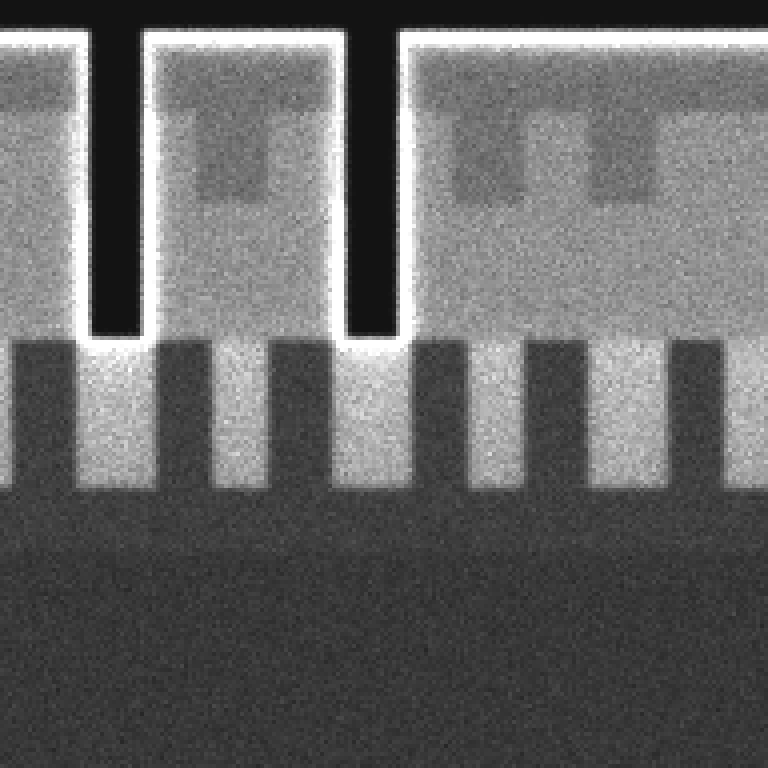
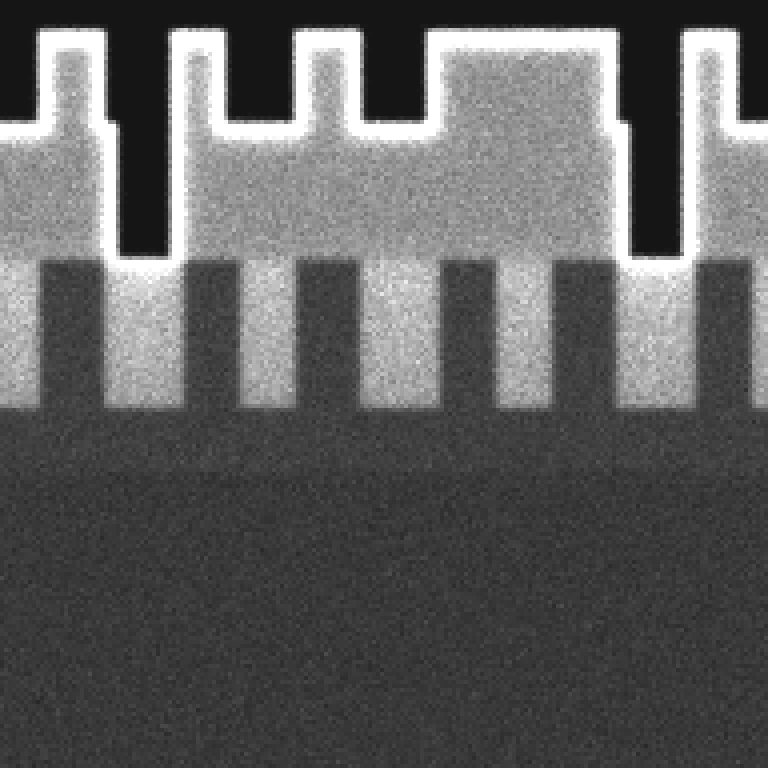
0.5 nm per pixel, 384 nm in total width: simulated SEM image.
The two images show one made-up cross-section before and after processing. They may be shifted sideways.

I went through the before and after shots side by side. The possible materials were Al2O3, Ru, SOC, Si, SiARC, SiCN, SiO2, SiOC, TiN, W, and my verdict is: removed, SOC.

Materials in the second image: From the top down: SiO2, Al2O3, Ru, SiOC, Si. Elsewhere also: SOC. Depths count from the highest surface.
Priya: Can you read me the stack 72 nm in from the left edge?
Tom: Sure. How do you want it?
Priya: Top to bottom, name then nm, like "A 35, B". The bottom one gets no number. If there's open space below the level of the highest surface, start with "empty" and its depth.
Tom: empty 114, Ru 74, SiOC 32, Si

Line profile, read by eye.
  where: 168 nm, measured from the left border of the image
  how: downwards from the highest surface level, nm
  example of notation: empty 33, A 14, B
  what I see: SiO2 102, Al2O3 12, SiOC 106, Si